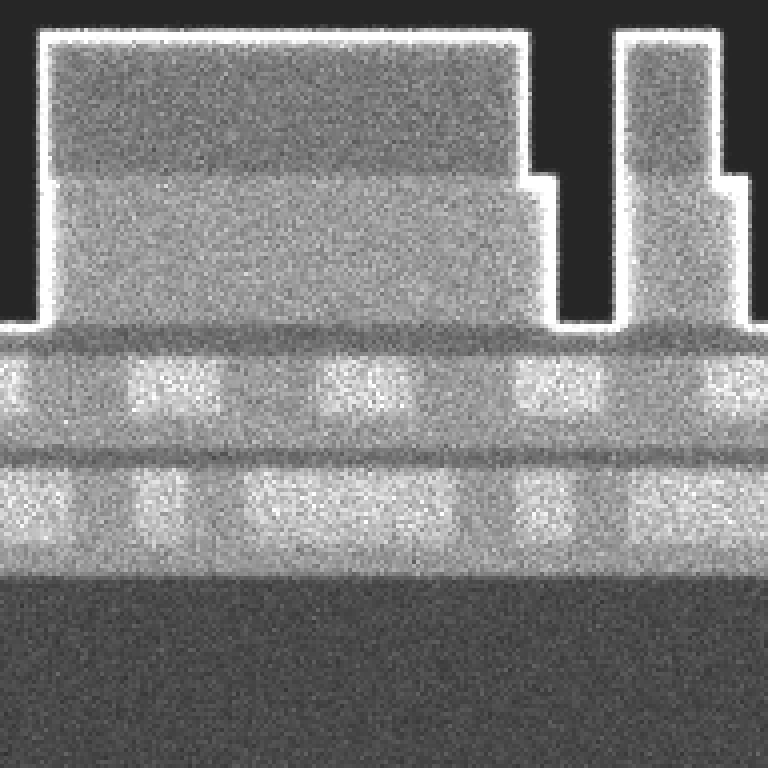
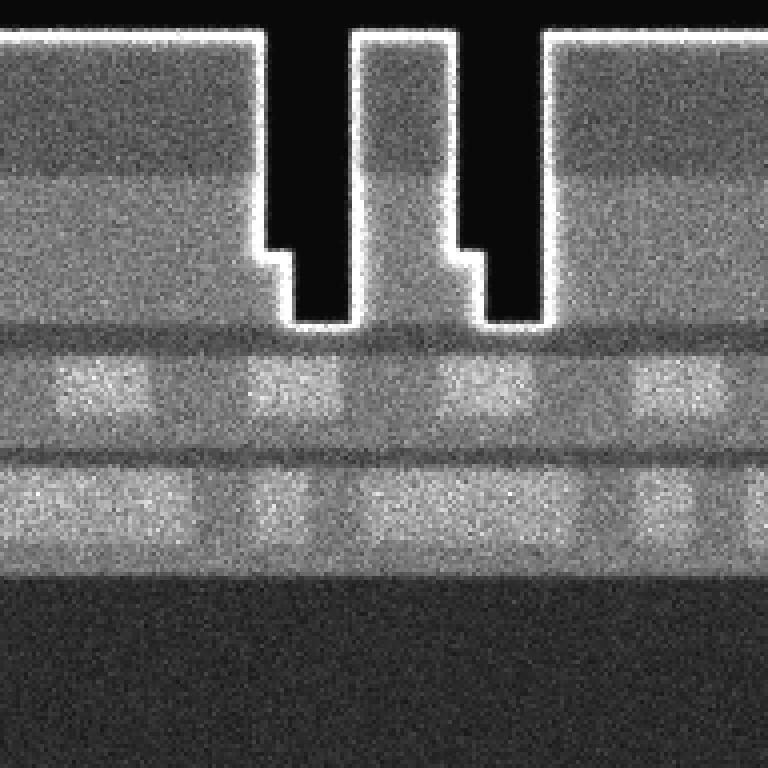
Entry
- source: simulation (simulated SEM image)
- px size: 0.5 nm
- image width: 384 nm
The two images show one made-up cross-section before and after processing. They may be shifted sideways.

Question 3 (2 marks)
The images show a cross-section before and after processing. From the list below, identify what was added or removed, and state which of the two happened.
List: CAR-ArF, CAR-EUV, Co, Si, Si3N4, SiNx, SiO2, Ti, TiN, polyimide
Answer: SiO2 was removed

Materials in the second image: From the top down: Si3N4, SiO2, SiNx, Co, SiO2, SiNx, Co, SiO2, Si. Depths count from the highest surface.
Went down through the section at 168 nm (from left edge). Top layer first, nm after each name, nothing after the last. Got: empty 146, SiNx 16, Co 30, SiO2 16, SiNx 10, SiO2 54, Si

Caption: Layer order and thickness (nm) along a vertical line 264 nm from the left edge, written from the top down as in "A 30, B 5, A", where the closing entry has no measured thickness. empty 146, SiNx 16, Co 30, SiO2 16, SiNx 10, Co 38, SiO2 16, Si